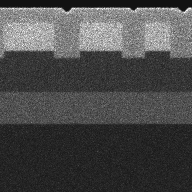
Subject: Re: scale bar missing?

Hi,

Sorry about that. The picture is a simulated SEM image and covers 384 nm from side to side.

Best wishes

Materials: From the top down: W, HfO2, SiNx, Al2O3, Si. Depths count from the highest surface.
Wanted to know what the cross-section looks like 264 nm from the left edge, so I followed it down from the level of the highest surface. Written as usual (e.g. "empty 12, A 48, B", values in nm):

empty 6, W 94, SiNx 68, Al2O3 64, Si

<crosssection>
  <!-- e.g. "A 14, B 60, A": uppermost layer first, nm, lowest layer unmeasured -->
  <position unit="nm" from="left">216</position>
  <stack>W 30, HfO2 56, SiNx 82, Al2O3 64, Si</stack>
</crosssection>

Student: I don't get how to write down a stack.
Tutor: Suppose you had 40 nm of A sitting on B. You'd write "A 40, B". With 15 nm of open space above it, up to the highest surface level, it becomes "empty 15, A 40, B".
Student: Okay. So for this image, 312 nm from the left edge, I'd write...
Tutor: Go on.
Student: W 30, HfO2 56, SiNx 82, Al2O3 64, Si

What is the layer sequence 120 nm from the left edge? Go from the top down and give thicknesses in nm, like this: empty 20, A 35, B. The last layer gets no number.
W 100, SiNx 68, Al2O3 64, Si